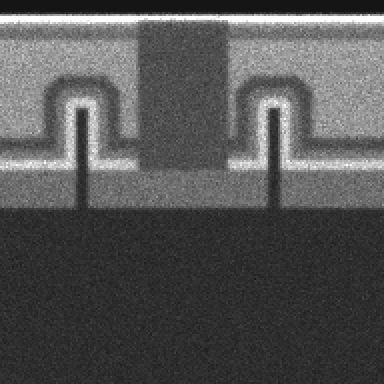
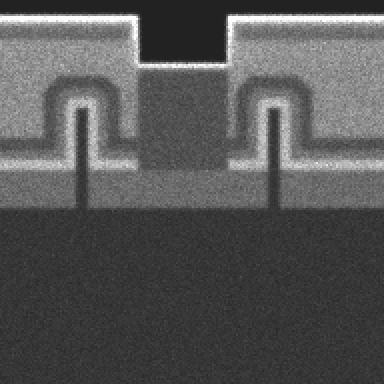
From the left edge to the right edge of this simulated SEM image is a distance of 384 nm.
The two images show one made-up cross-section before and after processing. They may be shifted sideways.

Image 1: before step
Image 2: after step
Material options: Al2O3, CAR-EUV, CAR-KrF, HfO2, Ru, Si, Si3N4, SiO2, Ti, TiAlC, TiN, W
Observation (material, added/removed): Si3N4, removed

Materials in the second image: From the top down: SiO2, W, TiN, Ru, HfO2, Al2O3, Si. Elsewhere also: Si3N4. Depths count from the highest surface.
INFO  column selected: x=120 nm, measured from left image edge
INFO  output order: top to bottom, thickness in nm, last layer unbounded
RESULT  SiO2 24, W 98, TiN 12, Ru 10, HfO2 10, Al2O3 38, Si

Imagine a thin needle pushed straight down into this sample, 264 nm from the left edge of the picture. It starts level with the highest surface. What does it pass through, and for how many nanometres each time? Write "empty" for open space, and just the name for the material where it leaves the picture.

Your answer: SiO2 24, W 36, TiN 12, Ru 10, HfO2 72, Al2O3 38, Si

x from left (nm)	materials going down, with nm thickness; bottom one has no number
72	SiO2 24, W 36, TiN 12, Ru 10, HfO2 72, Al2O3 38, Si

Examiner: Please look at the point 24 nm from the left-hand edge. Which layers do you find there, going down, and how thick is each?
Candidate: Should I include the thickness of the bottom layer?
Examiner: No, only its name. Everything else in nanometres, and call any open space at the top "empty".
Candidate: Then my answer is SiO2 24, W 98, TiN 12, Ru 10, HfO2 10, Al2O3 38, Si